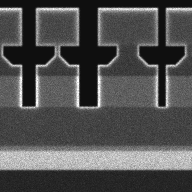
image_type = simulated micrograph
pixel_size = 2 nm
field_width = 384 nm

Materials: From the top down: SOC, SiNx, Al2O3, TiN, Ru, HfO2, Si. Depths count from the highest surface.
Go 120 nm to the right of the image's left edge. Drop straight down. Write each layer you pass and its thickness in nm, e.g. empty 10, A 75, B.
SOC 76, empty 20, SiNx 40, Al2O3 62, TiN 78, Ru 10, HfO2 38, Si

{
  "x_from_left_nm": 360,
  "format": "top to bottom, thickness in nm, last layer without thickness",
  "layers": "SOC 76, empty 28, SiNx 32, Al2O3 62, TiN 78, Ru 10, HfO2 38, Si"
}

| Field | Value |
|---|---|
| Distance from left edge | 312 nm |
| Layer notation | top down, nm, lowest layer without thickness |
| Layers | SOC 76, empty 38, SiNx 22, Al2O3 62, TiN 78, Ru 10, HfO2 38, Si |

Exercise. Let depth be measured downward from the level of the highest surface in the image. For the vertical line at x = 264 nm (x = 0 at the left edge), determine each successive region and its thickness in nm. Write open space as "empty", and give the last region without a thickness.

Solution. SOC 76, SiNx 60, Al2O3 62, TiN 78, Ru 10, HfO2 38, Si